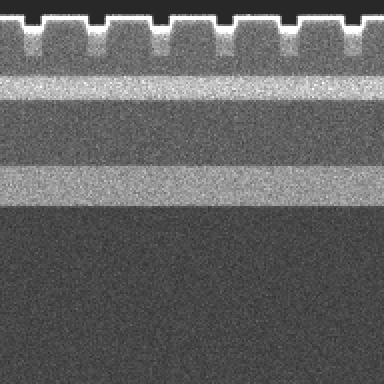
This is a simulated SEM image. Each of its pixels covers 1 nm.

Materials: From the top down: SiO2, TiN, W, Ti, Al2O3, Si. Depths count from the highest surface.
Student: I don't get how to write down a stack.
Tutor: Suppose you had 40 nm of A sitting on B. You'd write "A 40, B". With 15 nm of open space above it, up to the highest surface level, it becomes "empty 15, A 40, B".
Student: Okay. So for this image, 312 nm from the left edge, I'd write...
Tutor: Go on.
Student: TiN 60, W 24, Ti 66, Al2O3 40, Si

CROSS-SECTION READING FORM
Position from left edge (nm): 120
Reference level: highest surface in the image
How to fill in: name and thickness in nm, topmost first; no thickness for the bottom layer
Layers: TiN 60, W 24, Ti 66, Al2O3 40, Si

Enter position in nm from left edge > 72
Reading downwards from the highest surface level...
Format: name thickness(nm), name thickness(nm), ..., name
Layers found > TiN 60, W 24, Ti 66, Al2O3 40, Si